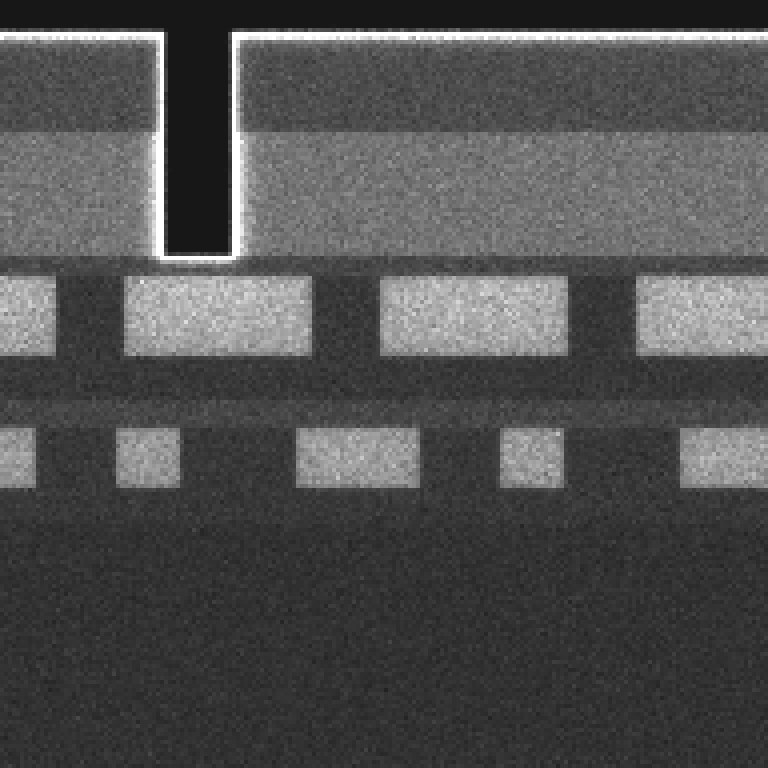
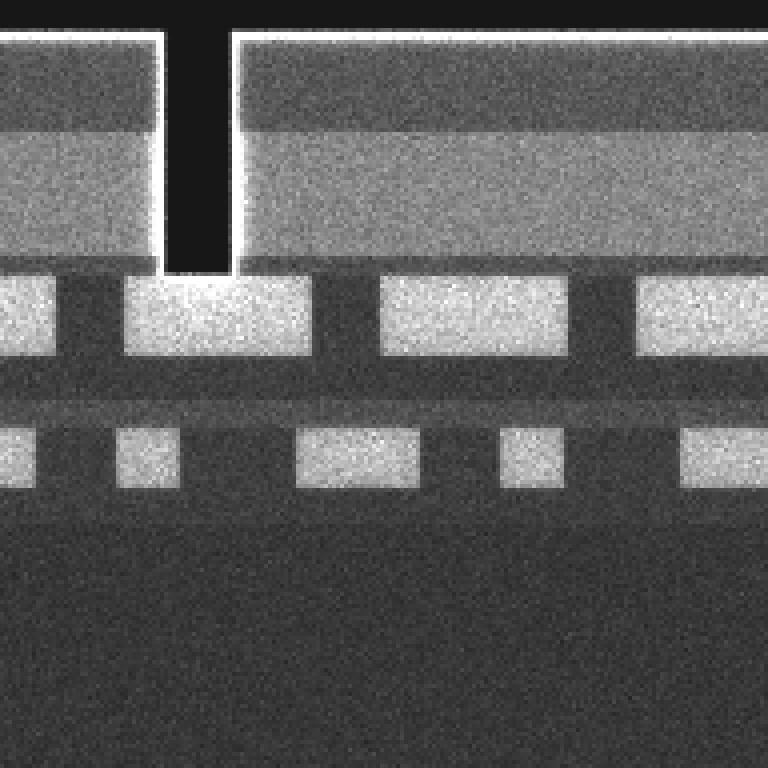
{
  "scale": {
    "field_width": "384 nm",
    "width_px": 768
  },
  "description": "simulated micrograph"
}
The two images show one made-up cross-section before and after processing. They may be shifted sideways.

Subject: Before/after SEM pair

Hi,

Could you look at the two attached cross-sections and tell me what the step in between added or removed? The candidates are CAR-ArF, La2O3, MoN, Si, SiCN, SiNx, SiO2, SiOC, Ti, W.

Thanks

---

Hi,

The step removed SiCN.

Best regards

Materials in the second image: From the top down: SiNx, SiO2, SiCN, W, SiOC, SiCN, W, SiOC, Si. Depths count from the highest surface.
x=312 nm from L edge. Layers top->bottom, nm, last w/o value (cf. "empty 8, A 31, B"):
SiNx 50, SiO2 62, SiCN 10, SiOC 62, SiCN 14, SiOC 48, Si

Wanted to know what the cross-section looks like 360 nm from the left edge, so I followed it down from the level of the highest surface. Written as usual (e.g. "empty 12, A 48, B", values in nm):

SiNx 50, SiO2 62, SiCN 10, W 40, SiOC 22, SiCN 14, W 30, SiOC 18, Si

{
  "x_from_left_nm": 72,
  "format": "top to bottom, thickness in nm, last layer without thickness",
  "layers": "SiNx 50, SiO2 62, SiCN 10, W 40, SiOC 22, SiCN 14, W 30, SiOC 18, Si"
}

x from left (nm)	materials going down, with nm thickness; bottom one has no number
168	SiNx 50, SiO2 62, SiCN 10, SiOC 62, SiCN 14, W 30, SiOC 18, Si